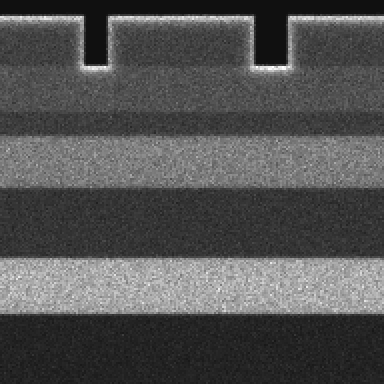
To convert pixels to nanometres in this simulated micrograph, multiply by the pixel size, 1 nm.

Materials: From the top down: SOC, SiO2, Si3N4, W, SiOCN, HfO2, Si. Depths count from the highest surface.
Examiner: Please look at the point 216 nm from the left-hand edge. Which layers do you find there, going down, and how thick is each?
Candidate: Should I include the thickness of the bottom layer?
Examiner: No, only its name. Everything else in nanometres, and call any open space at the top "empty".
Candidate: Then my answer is SOC 50, SiO2 46, Si3N4 24, W 52, SiOCN 70, HfO2 56, Si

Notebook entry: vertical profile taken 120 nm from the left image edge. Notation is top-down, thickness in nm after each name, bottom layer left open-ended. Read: SOC 50, SiO2 46, Si3N4 24, W 52, SiOCN 70, HfO2 56, Si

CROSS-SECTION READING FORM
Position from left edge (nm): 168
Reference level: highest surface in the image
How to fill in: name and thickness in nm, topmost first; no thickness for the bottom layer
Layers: SOC 50, SiO2 46, Si3N4 24, W 52, SiOCN 70, HfO2 56, Si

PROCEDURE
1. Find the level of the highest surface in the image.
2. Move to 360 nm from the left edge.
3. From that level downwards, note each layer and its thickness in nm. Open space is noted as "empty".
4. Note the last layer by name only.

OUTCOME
SOC 50, SiO2 46, Si3N4 24, W 52, SiOCN 70, HfO2 56, Si